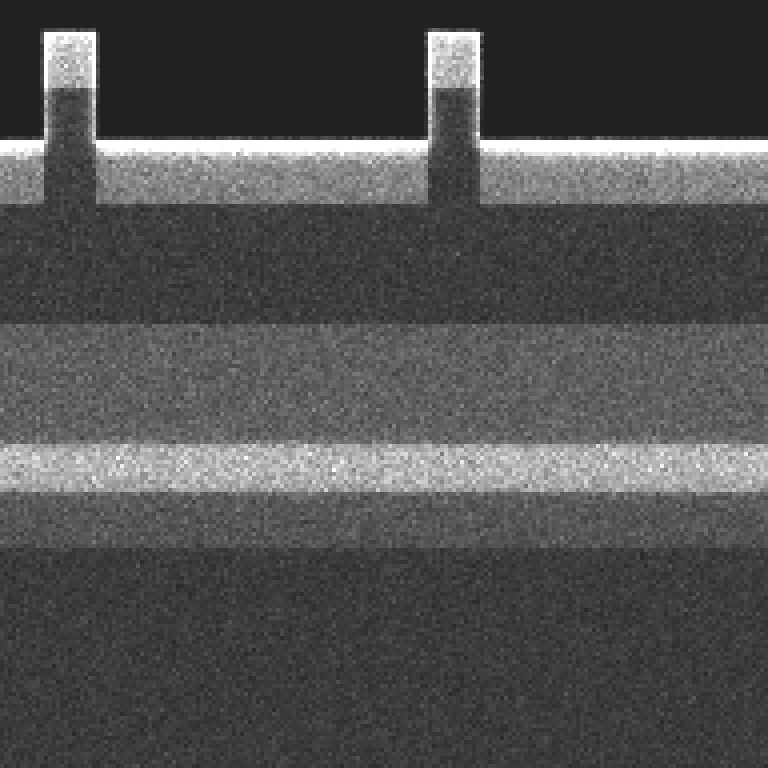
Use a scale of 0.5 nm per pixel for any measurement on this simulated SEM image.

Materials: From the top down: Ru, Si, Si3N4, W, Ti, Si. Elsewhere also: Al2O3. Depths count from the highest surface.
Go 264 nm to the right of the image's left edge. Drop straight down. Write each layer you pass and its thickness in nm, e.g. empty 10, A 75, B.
empty 54, Al2O3 32, Si 60, Si3N4 60, W 24, Ti 28, Si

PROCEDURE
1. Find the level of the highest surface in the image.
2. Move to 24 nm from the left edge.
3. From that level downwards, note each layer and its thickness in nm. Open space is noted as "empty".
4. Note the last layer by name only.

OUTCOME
Ru 28, Si 118, Si3N4 60, W 24, Ti 28, Si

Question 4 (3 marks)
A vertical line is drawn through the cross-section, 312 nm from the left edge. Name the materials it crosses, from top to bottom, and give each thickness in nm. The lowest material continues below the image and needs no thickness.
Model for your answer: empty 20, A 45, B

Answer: empty 54, Al2O3 32, Si 60, Si3N4 60, W 24, Ti 28, Si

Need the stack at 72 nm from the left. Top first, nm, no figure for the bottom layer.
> empty 54, Al2O3 32, Si 60, Si3N4 60, W 24, Ti 28, Si